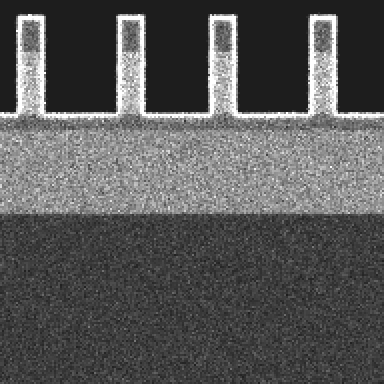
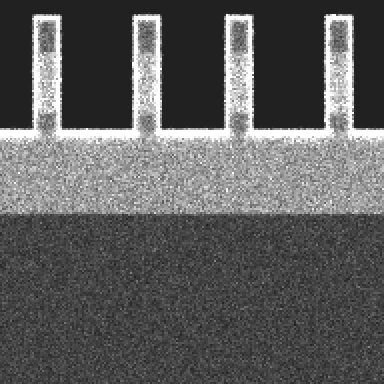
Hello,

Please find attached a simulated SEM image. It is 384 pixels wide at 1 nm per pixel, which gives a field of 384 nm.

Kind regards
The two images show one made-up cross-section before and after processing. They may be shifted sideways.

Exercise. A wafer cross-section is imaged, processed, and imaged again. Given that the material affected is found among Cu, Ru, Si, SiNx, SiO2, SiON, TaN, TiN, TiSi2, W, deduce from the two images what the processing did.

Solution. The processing removed TiN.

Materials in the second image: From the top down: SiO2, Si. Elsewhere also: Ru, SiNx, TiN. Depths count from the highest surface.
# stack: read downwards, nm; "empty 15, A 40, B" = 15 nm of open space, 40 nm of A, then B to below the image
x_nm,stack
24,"empty 114, SiO2 84, Si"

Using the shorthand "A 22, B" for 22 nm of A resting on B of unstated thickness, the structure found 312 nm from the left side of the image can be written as empty 114, SiO2 84, Si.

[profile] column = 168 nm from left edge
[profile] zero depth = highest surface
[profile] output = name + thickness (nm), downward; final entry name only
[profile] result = empty 114, SiO2 84, Si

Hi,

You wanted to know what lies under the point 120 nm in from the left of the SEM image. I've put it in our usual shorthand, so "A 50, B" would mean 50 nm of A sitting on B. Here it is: empty 114, SiO2 84, Si